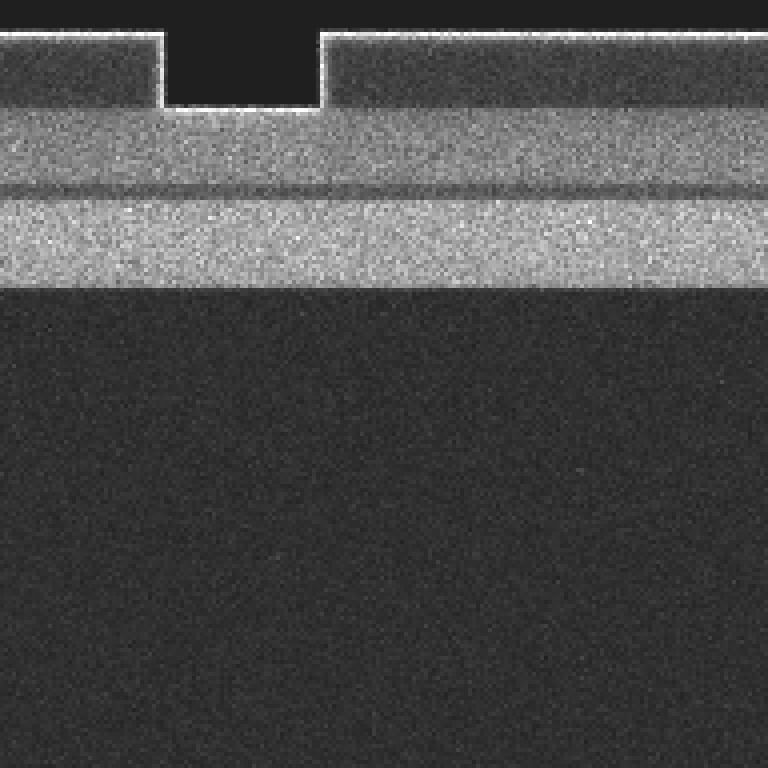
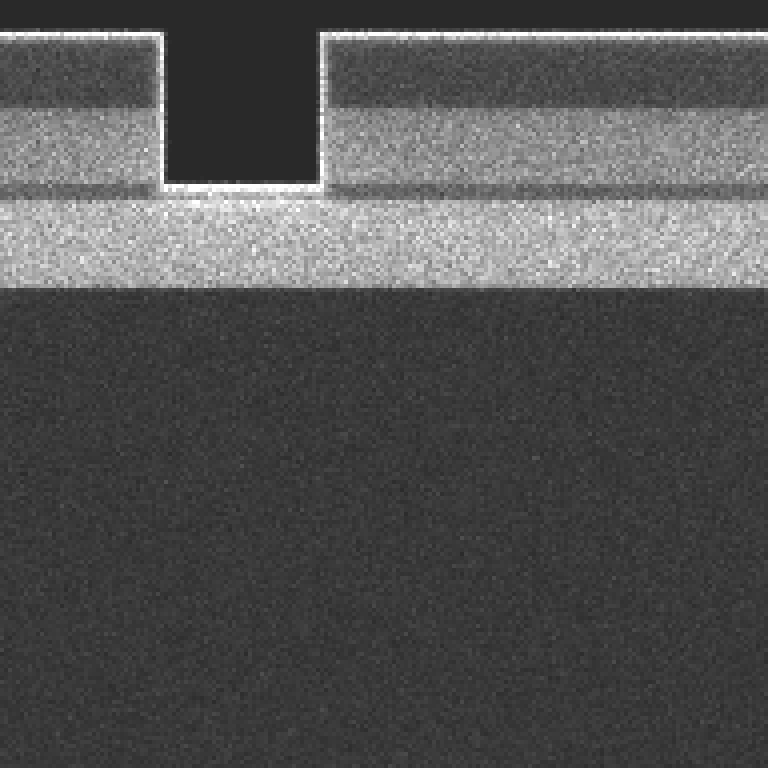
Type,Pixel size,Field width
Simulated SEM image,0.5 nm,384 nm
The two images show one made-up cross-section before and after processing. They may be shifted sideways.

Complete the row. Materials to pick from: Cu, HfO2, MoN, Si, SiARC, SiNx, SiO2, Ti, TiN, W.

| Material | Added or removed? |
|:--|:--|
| W | removed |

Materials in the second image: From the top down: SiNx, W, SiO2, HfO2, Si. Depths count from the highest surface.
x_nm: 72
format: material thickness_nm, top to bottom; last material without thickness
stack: SiNx 38, W 38, SiO2 8, HfO2 44, Si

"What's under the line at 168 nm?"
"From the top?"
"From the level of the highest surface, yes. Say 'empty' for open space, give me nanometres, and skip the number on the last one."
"SiNx 38, W 38, SiO2 8, HfO2 44, Si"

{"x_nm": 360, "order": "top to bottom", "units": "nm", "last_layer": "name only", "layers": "SiNx 38, W 38, SiO2 8, HfO2 44, Si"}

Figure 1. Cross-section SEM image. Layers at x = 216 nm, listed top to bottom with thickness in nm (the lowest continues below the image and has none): SiNx 38, W 38, SiO2 8, HfO2 44, Si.